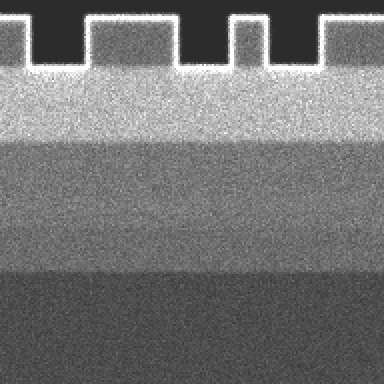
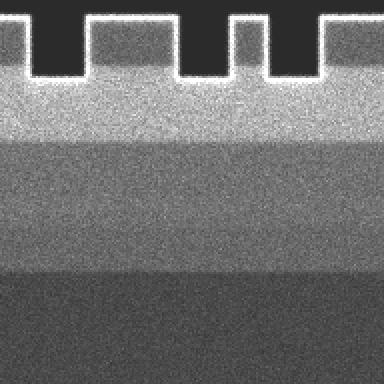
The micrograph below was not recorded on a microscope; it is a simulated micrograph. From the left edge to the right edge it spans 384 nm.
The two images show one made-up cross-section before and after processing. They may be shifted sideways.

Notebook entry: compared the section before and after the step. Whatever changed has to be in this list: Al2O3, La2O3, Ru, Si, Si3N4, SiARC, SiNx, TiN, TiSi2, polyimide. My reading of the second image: Ru removed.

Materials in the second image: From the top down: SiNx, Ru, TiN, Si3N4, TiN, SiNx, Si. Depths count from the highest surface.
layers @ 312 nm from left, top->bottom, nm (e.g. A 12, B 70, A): empty 62, Ru 64, TiN 54, Si3N4 16, TiN 16, SiNx 44, Si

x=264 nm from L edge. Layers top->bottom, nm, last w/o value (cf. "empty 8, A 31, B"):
SiNx 50, Ru 76, TiN 54, Si3N4 16, TiN 16, SiNx 44, Si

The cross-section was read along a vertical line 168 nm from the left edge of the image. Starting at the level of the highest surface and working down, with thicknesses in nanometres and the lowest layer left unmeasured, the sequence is SiNx 50, Ru 76, TiN 54, Si3N4 16, TiN 16, SiNx 44, Si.